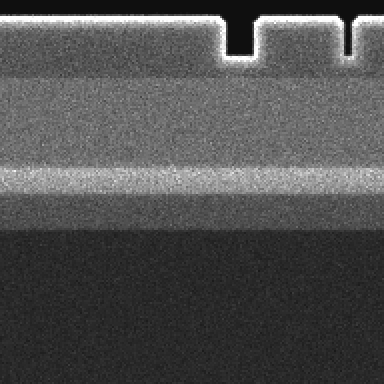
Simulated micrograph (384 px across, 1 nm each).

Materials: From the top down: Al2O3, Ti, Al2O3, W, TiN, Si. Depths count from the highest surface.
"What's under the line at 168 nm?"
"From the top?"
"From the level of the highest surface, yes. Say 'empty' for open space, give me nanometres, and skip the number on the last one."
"Al2O3 12, Ti 50, Al2O3 90, W 26, TiN 36, Si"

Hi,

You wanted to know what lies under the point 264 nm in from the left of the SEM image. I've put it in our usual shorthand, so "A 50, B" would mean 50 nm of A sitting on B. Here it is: Al2O3 52, Ti 10, Al2O3 90, W 26, TiN 36, Si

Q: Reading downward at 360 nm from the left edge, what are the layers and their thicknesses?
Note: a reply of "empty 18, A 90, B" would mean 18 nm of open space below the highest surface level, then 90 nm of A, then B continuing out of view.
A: Al2O3 52, Ti 10, Al2O3 90, W 26, TiN 36, Si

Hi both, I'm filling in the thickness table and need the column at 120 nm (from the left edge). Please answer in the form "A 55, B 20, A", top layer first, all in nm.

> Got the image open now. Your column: Al2O3 12, Ti 50, Al2O3 90, W 26, TiN 36, Si